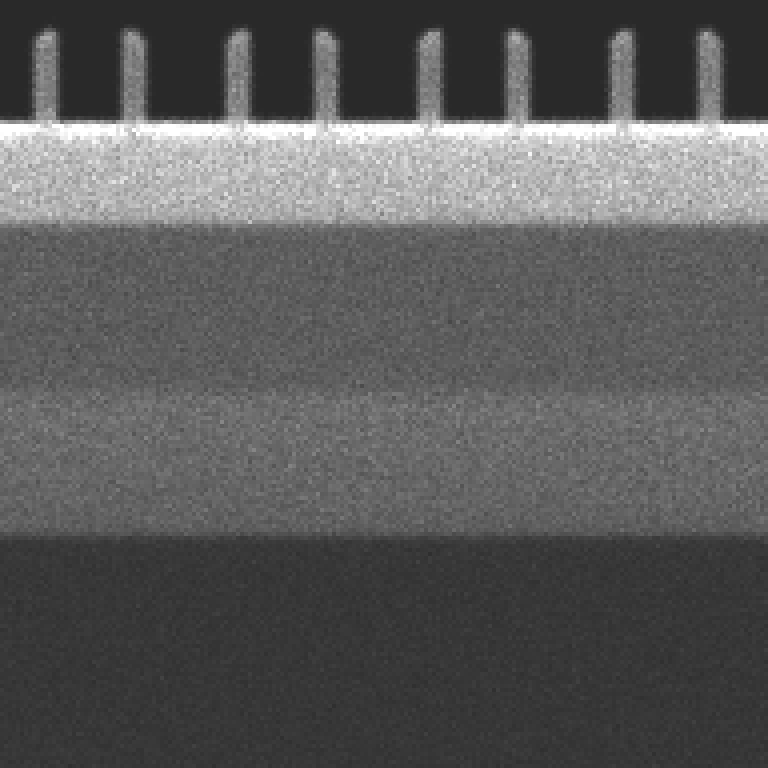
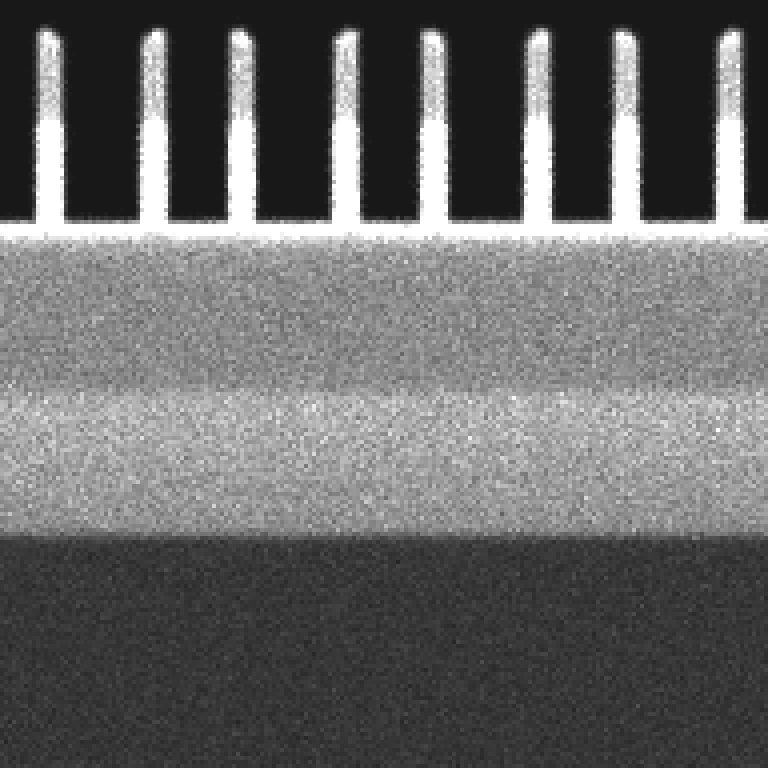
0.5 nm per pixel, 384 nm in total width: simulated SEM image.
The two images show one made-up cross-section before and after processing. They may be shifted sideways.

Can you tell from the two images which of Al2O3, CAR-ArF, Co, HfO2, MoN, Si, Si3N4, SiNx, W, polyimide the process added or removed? Yes, it removed HfO2.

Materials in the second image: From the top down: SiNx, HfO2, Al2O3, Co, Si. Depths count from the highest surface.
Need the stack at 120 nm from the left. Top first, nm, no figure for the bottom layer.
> SiNx 46, HfO2 50, Al2O3 84, Co 72, Si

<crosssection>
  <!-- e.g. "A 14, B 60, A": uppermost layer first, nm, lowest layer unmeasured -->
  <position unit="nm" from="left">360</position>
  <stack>empty 4, SiNx 42, HfO2 50, Al2O3 84, Co 72, Si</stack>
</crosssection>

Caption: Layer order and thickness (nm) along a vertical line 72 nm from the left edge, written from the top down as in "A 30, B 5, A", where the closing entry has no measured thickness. empty 4, SiNx 42, HfO2 50, Al2O3 84, Co 72, Si